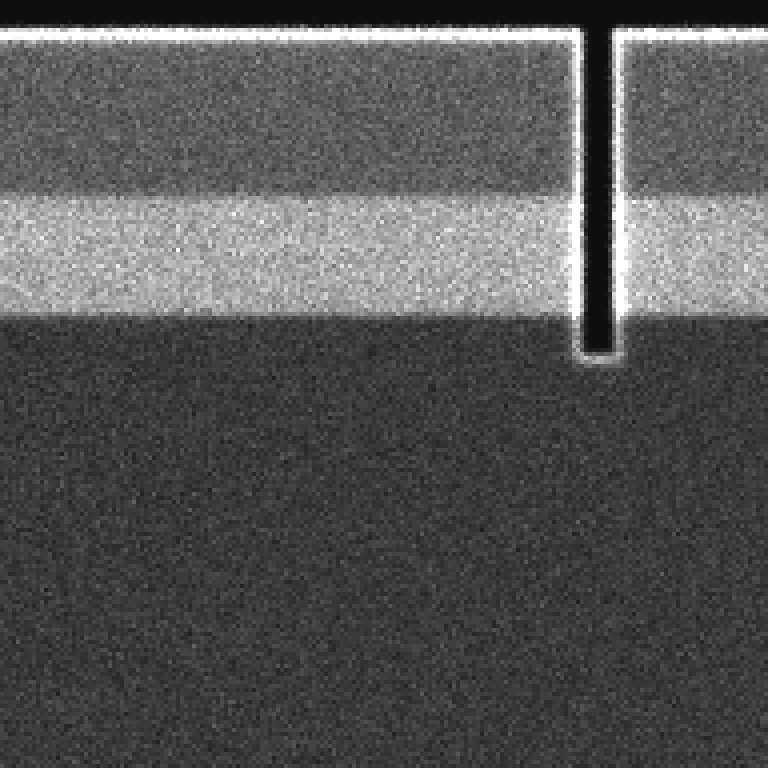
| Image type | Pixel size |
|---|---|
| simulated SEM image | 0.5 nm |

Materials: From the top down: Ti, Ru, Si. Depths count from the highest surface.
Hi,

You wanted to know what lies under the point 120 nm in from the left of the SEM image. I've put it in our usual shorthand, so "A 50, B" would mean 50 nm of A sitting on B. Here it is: Ti 82, Ru 60, Si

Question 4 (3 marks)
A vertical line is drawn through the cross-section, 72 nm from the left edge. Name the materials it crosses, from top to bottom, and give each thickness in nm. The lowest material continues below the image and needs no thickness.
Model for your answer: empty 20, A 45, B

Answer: Ti 82, Ru 60, Si